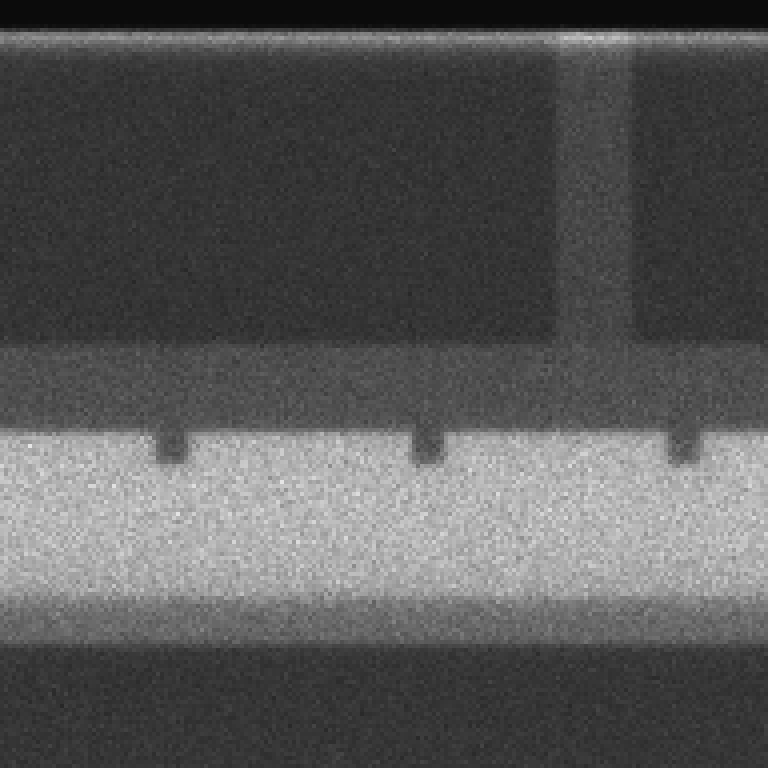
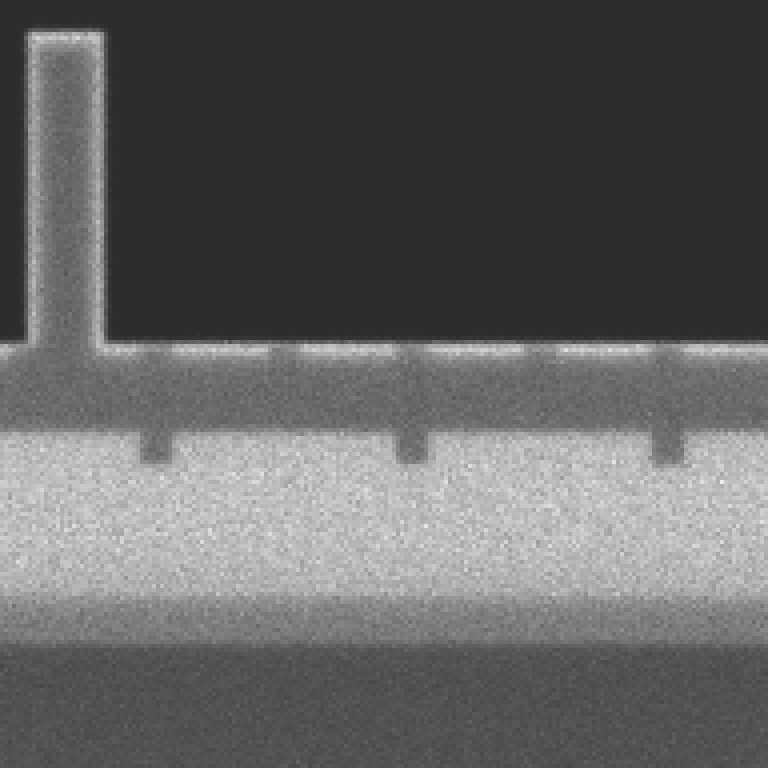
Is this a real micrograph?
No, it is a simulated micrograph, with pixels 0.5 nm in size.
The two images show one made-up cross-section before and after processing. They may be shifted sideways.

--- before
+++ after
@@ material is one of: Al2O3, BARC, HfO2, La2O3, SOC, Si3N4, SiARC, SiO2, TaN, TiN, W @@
SOC removed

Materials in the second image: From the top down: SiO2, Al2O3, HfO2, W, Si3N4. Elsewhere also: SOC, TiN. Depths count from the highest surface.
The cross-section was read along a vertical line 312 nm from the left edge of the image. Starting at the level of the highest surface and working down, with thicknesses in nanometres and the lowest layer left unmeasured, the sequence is empty 156, Al2O3 44, HfO2 82, W 24, Si3N4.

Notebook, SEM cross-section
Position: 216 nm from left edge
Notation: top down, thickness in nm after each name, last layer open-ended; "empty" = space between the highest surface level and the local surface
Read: empty 156, Al2O3 44, HfO2 82, W 24, Si3N4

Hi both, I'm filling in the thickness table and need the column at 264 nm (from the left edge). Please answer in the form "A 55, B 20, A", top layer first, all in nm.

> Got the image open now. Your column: empty 156, TiN 44, HfO2 82, W 24, Si3N4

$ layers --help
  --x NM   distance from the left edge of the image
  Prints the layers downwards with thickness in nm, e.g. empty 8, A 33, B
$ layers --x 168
empty 156, Al2O3 44, HfO2 82, W 24, Si3N4